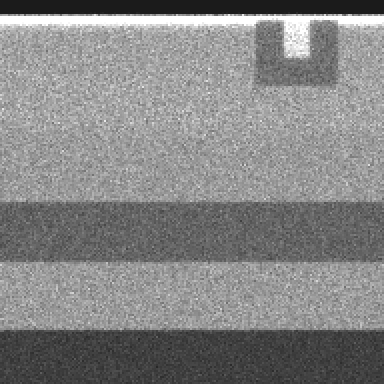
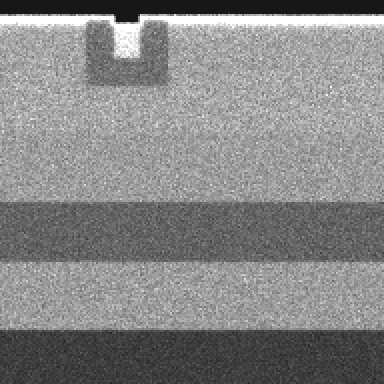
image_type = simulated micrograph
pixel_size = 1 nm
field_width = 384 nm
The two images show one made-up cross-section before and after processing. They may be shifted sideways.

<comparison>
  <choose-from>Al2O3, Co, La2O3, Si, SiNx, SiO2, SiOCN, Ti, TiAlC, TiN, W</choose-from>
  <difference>W removed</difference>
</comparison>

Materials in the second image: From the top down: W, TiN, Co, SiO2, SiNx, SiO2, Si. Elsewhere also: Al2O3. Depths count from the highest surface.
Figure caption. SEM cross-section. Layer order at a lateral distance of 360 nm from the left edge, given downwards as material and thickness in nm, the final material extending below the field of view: Al2O3 48, Co 68, SiO2 70, SiNx 60, SiO2 68, Si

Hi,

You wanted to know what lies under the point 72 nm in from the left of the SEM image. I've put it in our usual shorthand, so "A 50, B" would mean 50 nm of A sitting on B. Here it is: Al2O3 48, Co 68, SiO2 70, SiNx 60, SiO2 68, Si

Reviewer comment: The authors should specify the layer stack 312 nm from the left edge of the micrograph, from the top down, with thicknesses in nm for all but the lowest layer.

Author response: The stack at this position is Al2O3 48, Co 68, SiO2 70, SiNx 60, SiO2 68, Si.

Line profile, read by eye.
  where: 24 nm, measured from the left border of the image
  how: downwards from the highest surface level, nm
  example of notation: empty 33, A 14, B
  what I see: Al2O3 48, Co 68, SiO2 70, SiNx 60, SiO2 68, Si